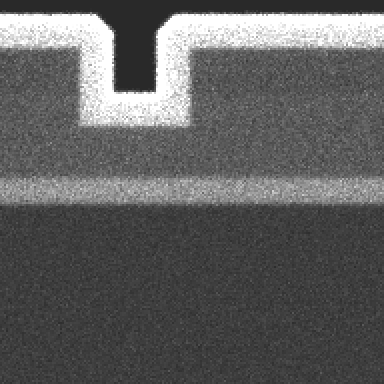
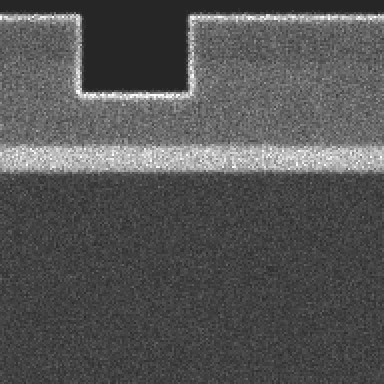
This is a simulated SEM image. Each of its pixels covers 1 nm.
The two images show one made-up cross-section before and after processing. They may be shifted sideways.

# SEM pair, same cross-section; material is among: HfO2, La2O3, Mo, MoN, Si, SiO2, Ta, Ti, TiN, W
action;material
removed;HfO2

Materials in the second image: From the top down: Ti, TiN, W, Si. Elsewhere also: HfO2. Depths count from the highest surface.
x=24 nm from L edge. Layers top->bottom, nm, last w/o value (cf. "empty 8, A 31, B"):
Ti 46, TiN 84, W 26, Si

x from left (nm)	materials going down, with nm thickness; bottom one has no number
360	Ti 46, TiN 84, W 26, Si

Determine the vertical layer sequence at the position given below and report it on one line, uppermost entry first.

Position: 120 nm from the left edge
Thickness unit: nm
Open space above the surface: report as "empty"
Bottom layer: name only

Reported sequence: empty 78, TiN 52, W 26, Si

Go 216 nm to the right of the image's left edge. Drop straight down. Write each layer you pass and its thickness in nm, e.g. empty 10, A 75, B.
Ti 46, TiN 84, W 26, Si